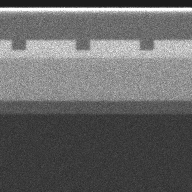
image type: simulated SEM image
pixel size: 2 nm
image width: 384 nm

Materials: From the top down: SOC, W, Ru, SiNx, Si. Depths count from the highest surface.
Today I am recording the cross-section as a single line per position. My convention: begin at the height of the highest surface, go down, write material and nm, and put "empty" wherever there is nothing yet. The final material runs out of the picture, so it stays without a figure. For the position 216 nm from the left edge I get SOC 64, W 36, Ru 86, SiNx 26, Si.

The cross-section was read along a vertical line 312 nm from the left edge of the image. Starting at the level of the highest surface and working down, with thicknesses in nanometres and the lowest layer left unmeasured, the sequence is SOC 64, W 36, Ru 86, SiNx 26, Si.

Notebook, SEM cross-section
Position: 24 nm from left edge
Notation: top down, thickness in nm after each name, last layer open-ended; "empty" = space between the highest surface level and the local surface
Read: SOC 84, W 16, Ru 86, SiNx 26, Si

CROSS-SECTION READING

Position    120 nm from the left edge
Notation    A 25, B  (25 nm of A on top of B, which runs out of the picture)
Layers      SOC 64, W 36, Ru 86, SiNx 26, Si